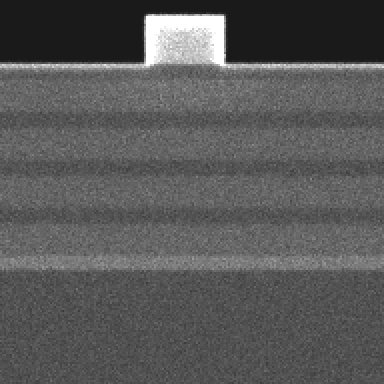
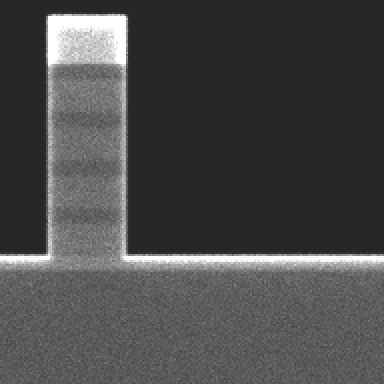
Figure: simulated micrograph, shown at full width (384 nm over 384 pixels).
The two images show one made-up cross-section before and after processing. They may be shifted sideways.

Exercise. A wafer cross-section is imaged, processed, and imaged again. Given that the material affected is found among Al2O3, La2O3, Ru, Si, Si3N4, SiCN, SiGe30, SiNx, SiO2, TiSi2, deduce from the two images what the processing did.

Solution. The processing removed Si and SiGe30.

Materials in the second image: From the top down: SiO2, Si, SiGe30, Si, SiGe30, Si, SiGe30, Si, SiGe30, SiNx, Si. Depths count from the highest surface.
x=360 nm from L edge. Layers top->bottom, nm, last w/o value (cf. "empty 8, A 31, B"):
empty 240, SiNx 14, Si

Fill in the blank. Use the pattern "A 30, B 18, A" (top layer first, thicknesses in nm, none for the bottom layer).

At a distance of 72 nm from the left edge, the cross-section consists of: SiO2 48, Si 16, SiGe30 32, Si 16, SiGe30 32, Si 16, SiGe30 32, Si 16, SiGe30 32, SiNx 14, Si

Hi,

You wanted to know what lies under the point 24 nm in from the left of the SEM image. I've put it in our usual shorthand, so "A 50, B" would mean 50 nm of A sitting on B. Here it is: empty 240, SiNx 14, Si